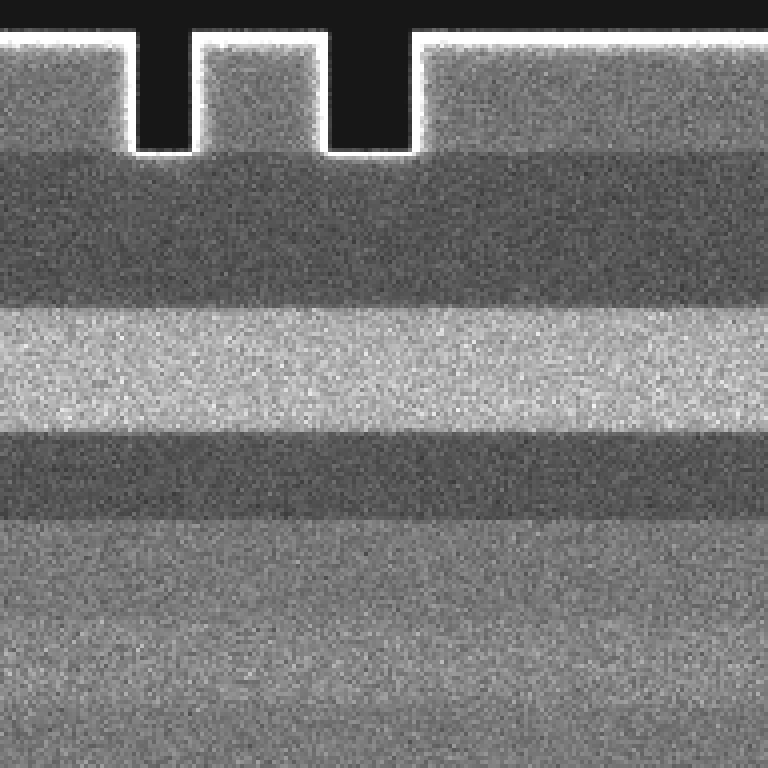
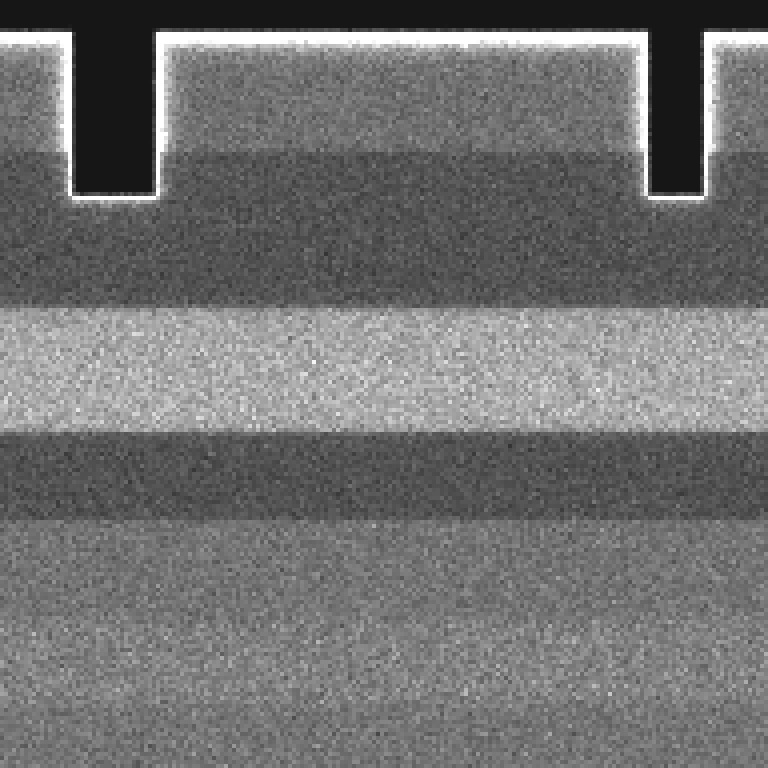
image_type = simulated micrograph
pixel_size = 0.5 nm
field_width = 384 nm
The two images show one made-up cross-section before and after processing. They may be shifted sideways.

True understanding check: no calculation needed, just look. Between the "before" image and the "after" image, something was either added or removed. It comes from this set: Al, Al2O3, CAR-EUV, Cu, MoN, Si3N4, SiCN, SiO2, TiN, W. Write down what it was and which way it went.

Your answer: TiN (removed)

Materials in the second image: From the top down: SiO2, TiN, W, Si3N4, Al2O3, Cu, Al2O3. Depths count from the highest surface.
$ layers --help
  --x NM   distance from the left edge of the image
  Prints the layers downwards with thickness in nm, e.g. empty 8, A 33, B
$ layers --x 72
empty 82, TiN 56, W 62, Si3N4 44, Al2O3 50, Cu 42, Al2O3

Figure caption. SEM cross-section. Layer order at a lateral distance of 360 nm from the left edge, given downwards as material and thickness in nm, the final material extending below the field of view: SiO2 60, TiN 78, W 62, Si3N4 44, Al2O3 50, Cu 42, Al2O3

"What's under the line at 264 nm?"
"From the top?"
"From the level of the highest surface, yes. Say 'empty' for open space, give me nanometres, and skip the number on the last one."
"SiO2 60, TiN 78, W 62, Si3N4 44, Al2O3 50, Cu 42, Al2O3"